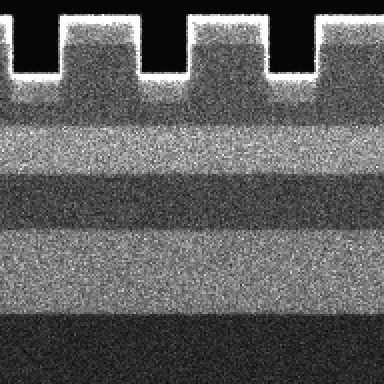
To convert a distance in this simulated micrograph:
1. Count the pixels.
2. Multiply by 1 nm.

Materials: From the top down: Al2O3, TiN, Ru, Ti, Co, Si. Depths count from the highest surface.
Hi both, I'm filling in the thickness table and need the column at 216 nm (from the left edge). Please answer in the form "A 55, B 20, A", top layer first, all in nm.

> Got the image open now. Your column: Al2O3 28, TiN 82, Ru 48, Ti 56, Co 84, Si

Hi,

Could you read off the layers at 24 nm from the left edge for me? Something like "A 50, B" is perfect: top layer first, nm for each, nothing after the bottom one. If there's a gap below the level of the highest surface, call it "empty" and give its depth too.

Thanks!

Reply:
empty 58, Al2O3 28, TiN 24, Ru 48, Ti 56, Co 84, Si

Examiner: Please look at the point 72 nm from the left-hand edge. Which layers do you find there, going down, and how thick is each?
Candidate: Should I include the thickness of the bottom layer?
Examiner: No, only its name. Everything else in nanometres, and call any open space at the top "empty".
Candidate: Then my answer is Al2O3 28, TiN 82, Ru 48, Ti 56, Co 84, Si